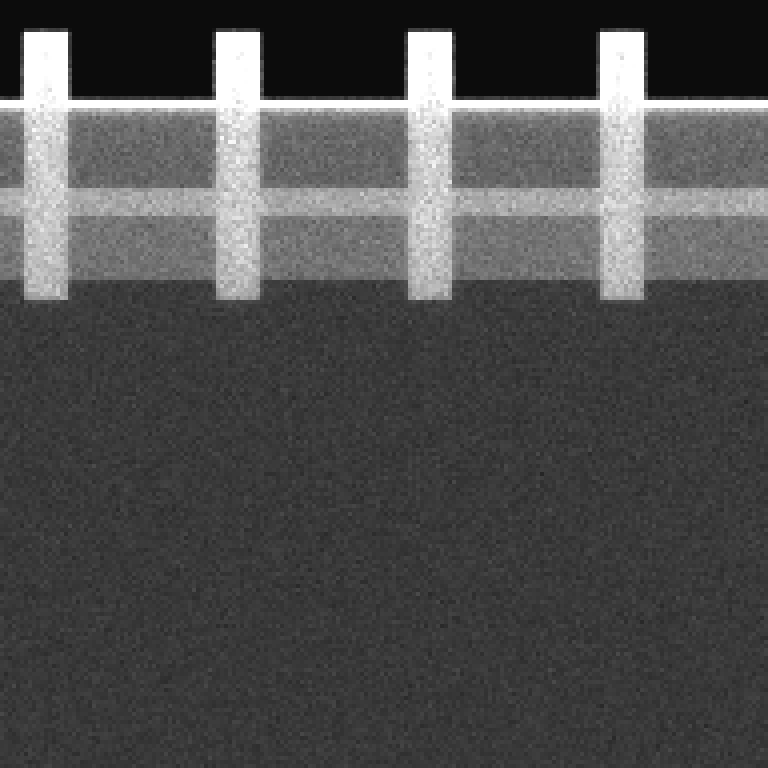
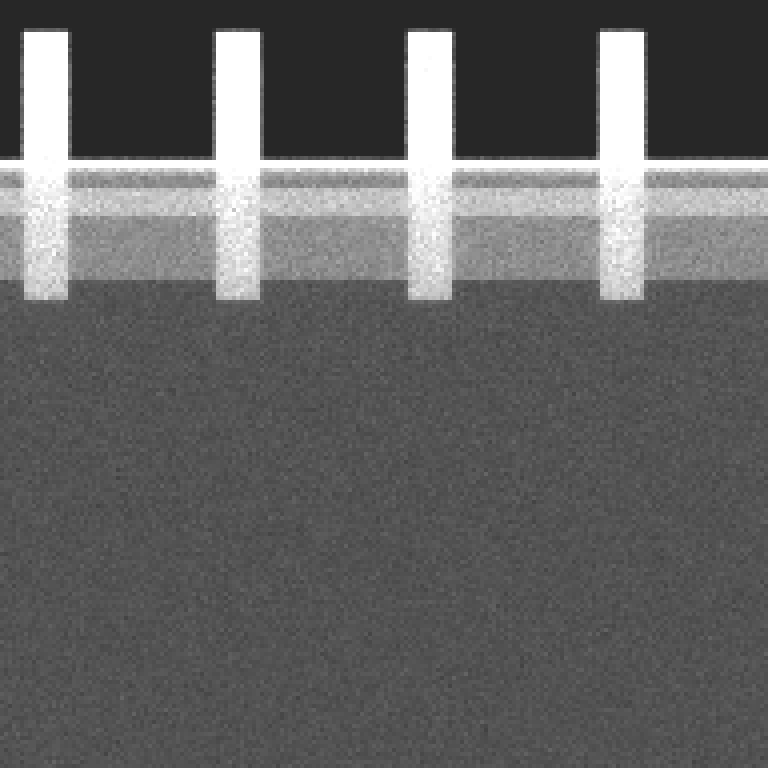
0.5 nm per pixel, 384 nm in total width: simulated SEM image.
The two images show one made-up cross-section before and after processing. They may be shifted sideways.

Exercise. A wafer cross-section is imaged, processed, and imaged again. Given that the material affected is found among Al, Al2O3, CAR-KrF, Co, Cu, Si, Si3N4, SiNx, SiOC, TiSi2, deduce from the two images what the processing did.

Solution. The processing removed SiNx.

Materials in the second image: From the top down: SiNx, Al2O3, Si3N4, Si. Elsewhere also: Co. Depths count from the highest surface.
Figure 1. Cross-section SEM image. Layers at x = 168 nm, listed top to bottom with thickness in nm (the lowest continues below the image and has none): empty 64, SiNx 14, Al2O3 14, Si3N4 32, Si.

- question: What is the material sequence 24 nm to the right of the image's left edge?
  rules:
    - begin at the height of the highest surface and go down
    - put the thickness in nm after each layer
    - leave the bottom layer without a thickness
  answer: Al2O3 14, Co 120, Si